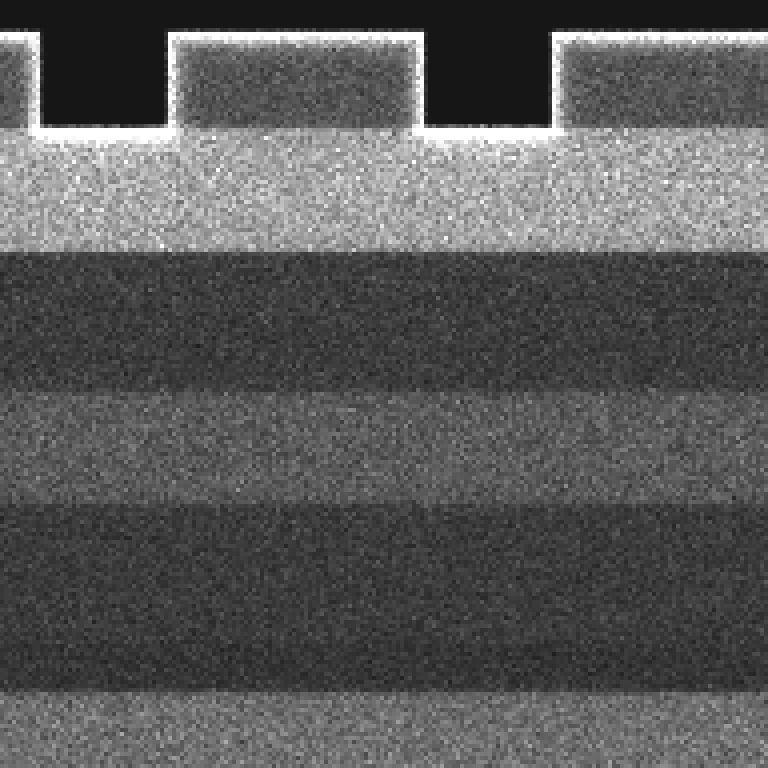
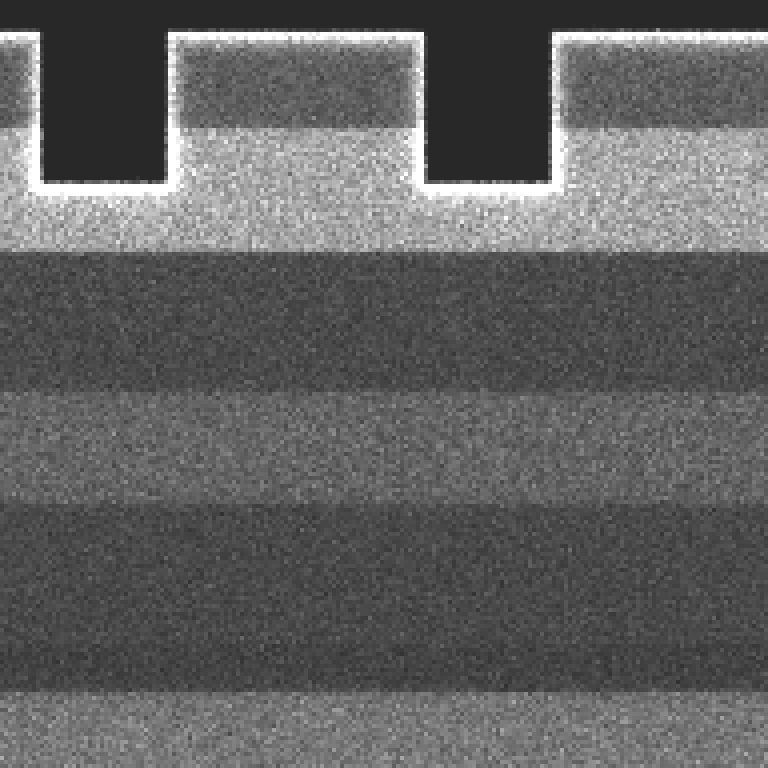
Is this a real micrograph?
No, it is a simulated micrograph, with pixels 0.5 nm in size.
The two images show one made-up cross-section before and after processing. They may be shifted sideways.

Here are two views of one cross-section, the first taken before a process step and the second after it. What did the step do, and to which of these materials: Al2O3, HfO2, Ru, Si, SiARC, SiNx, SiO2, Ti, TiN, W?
It removed HfO2.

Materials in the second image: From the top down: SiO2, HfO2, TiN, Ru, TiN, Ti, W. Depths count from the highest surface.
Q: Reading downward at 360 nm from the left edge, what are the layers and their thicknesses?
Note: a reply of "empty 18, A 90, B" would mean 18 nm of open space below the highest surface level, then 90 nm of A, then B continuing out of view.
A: SiO2 48, HfO2 62, TiN 70, Ru 56, TiN 70, Ti 24, W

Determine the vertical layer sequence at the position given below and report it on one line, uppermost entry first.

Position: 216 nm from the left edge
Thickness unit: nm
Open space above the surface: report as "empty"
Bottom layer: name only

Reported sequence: empty 76, HfO2 34, TiN 70, Ru 56, TiN 70, Ti 24, W